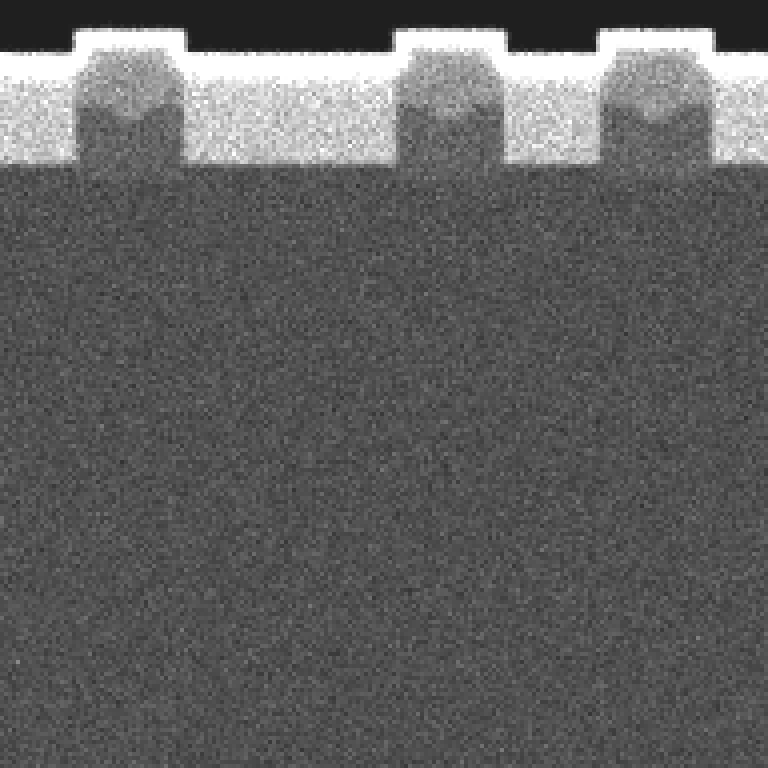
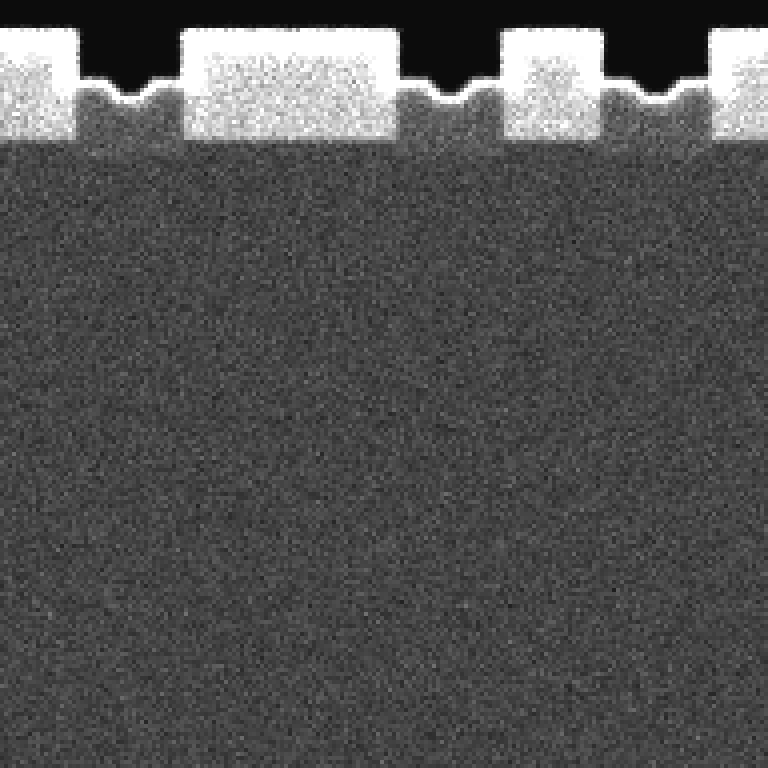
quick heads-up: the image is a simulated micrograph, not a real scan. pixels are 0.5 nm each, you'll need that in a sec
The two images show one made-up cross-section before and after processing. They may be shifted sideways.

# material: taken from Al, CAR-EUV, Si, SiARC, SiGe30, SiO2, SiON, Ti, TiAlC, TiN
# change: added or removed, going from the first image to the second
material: SiARC
change: removed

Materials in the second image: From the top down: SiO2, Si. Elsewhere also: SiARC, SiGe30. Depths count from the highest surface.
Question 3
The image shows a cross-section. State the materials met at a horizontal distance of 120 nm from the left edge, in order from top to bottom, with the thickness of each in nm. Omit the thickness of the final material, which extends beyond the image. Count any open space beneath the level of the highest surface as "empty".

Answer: SiO2 54, Si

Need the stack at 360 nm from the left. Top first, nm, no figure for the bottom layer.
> SiO2 54, Si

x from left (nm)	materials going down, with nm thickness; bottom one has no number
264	SiO2 54, Si